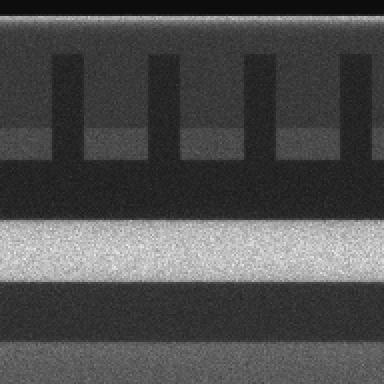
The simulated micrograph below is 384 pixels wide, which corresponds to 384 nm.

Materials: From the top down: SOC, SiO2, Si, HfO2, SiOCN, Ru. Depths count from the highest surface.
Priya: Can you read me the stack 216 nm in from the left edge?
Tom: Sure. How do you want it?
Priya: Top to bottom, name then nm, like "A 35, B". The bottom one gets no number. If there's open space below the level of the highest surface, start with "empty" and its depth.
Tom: SOC 112, SiO2 32, Si 60, HfO2 62, SiOCN 60, Ru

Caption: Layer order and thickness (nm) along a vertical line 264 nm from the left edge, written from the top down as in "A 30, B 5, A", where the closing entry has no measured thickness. SOC 38, Si 166, HfO2 62, SiOCN 60, Ru